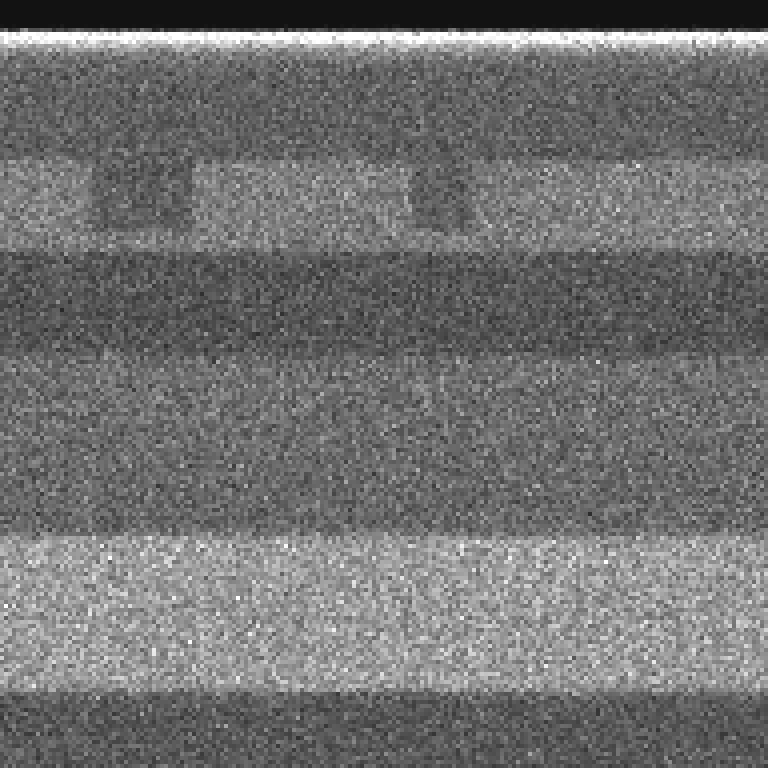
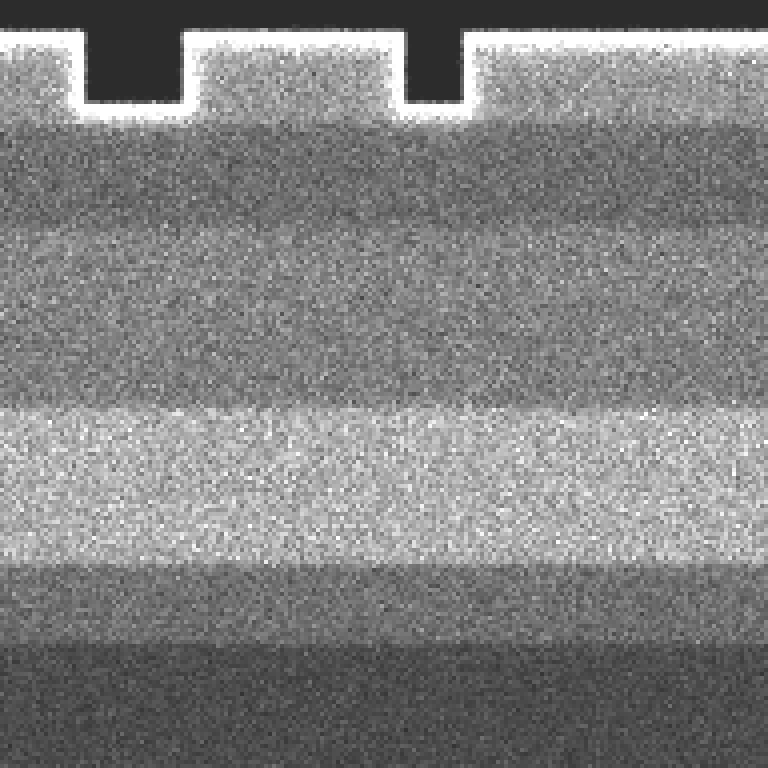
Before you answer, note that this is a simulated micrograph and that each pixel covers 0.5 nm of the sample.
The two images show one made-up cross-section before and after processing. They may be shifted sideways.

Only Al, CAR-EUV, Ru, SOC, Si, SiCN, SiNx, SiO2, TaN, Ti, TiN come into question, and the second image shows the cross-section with SOC removed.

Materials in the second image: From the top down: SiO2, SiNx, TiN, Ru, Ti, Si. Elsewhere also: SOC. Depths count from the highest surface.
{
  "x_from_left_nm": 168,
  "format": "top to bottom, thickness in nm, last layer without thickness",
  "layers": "SiO2 46, SiNx 52, TiN 90, Ru 78, Ti 40, Si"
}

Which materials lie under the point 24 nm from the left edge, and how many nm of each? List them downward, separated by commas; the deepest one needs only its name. SiO2 46, SiNx 52, TiN 90, Ru 78, Ti 40, Si